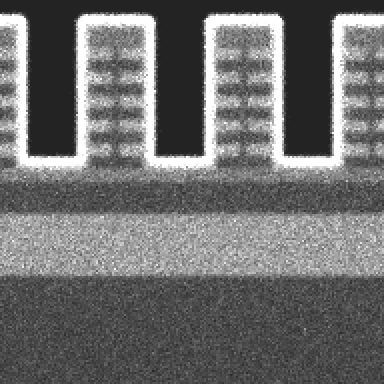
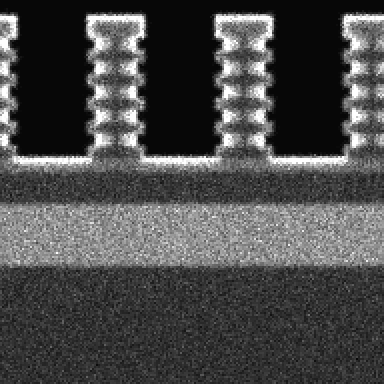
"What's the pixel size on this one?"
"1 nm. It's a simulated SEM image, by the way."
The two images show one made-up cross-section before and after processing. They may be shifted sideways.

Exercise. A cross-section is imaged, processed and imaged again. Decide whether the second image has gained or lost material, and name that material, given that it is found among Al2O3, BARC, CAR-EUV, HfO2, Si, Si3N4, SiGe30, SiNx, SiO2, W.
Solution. removed: Al2O3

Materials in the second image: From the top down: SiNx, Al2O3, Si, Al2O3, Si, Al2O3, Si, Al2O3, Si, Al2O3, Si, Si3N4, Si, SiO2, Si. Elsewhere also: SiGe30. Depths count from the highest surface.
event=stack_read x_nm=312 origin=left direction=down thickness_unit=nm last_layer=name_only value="empty 142, Si3N4 14, Si 32, SiO2 62, Si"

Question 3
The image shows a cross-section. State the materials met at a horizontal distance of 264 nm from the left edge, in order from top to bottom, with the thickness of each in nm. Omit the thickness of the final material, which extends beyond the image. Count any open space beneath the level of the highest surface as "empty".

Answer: SiNx 22, empty 12, Si 12, empty 12, Si 12, empty 12, Si 12, empty 12, Si 12, empty 12, Si 12, Si3N4 14, Si 32, SiO2 62, Si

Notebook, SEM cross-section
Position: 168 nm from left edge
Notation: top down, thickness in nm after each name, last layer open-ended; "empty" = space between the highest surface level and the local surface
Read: empty 142, Si3N4 14, Si 32, SiO2 62, Si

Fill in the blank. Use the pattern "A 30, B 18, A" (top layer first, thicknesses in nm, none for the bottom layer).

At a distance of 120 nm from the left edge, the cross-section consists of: SiNx 22, Al2O3 12, Si 12, Al2O3 12, Si 12, Al2O3 12, Si 12, Al2O3 12, Si 12, Al2O3 12, Si 12, Si3N4 14, Si 32, SiO2 62, Si